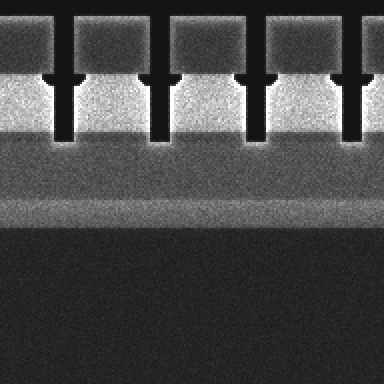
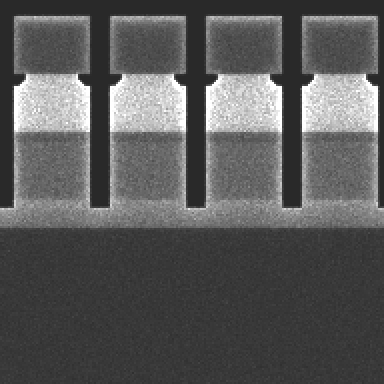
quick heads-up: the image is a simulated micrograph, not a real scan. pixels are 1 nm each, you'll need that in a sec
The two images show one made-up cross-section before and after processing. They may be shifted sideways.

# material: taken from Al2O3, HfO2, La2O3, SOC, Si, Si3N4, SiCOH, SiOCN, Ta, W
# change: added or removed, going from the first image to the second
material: Al2O3 and W
change: removed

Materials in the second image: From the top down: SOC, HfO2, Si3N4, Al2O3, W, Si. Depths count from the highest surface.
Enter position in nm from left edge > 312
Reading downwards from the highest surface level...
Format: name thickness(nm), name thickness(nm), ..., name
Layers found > SOC 58, empty 6, HfO2 52, Si3N4 10, Al2O3 58, W 28, Si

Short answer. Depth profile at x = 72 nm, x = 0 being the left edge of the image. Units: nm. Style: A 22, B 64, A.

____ SOC 58, HfO2 58, Si3N4 10, Al2O3 58, W 28, Si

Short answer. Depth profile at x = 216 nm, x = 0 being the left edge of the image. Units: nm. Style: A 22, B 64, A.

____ SOC 58, empty 6, HfO2 52, Si3N4 10, Al2O3 58, W 28, Si